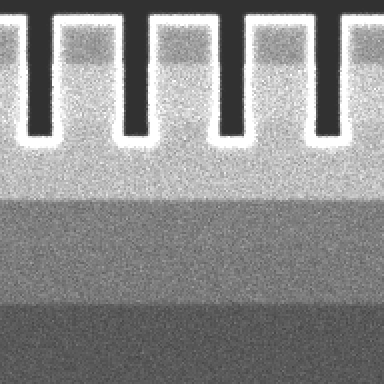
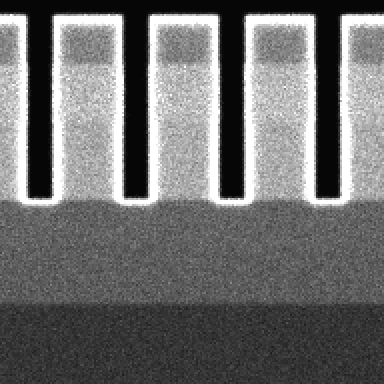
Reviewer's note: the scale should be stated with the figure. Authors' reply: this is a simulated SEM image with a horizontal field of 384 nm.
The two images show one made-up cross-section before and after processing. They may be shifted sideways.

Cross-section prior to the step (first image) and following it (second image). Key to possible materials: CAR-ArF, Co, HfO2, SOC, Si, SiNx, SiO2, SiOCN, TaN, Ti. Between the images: SiO2 was removed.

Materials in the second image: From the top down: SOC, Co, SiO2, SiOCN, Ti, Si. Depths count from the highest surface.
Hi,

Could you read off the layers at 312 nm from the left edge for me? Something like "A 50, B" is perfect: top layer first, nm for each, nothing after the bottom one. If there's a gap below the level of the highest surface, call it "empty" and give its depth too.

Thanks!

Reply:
SOC 48, Co 58, SiO2 78, SiOCN 46, Ti 58, Si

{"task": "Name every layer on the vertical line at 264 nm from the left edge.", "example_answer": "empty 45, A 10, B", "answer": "SOC 48, Co 58, SiO2 78, SiOCN 46, Ti 58, Si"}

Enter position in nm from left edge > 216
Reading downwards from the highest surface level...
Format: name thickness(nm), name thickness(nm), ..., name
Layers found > SOC 48, Co 58, SiO2 78, SiOCN 46, Ti 58, Si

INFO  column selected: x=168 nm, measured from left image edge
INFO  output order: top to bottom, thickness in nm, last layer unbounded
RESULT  SOC 48, Co 58, SiO2 78, SiOCN 46, Ti 58, Si